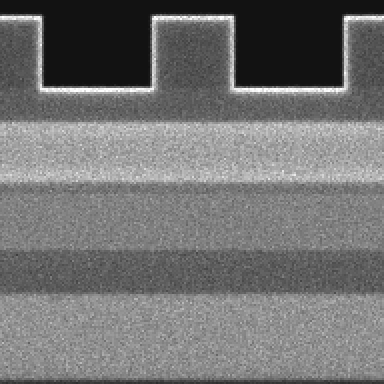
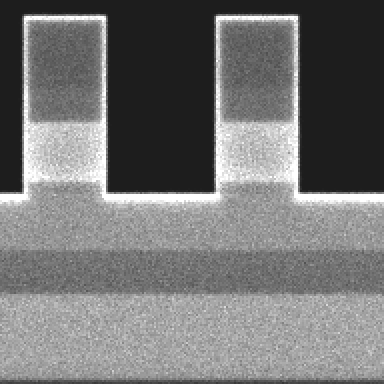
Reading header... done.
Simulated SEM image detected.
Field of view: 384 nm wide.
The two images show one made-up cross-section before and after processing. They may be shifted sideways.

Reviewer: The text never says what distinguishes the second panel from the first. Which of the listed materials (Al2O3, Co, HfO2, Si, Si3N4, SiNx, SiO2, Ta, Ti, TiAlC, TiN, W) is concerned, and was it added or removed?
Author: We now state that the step removed Si3N4 and TiN and W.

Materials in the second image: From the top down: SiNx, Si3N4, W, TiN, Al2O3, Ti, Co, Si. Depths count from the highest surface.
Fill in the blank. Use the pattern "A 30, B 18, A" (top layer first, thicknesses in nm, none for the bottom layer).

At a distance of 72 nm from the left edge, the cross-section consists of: SiNx 72, Si3N4 34, W 60, TiN 12, Al2O3 56, Ti 44, Co 86, Si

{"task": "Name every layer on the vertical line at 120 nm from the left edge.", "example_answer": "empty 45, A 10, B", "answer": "empty 178, Al2O3 56, Ti 44, Co 86, Si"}